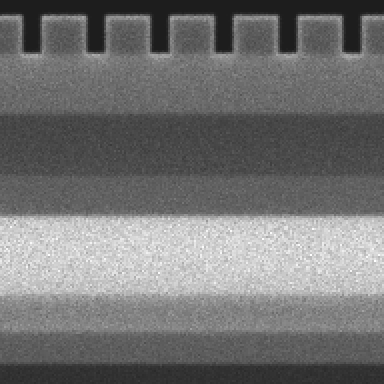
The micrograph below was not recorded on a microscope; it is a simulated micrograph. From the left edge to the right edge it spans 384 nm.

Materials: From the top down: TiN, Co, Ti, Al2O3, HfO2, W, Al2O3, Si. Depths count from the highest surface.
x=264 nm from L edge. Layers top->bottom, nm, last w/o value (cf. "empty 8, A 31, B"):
TiN 38, Co 60, Ti 62, Al2O3 40, HfO2 78, W 38, Al2O3 32, Si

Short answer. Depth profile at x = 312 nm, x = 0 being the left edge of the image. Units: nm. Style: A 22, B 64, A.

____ TiN 38, Co 60, Ti 62, Al2O3 40, HfO2 78, W 38, Al2O3 32, Si